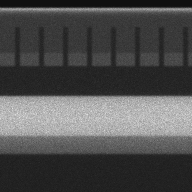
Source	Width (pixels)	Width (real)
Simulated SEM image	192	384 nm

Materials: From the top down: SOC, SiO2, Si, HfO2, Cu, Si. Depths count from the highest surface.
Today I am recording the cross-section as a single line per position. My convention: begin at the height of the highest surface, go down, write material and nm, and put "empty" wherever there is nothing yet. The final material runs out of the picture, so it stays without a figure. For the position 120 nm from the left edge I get SOC 90, SiO2 26, Si 60, HfO2 80, Cu 36, Si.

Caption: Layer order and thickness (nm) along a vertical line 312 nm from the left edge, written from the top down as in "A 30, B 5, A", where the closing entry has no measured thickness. SOC 90, SiO2 26, Si 60, HfO2 80, Cu 36, Si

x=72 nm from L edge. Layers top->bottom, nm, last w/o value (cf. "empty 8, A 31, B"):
SOC 90, SiO2 26, Si 60, HfO2 80, Cu 36, Si